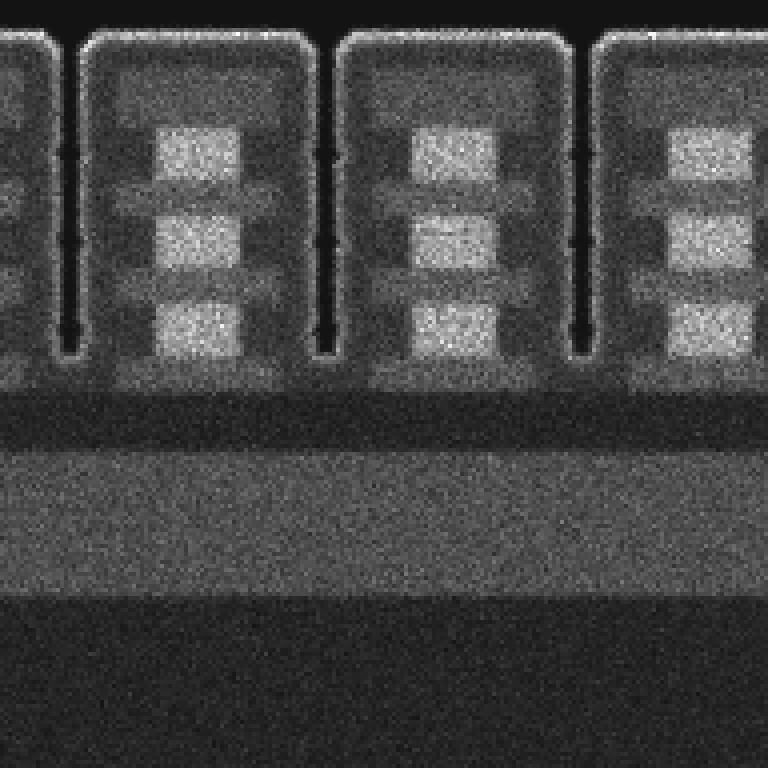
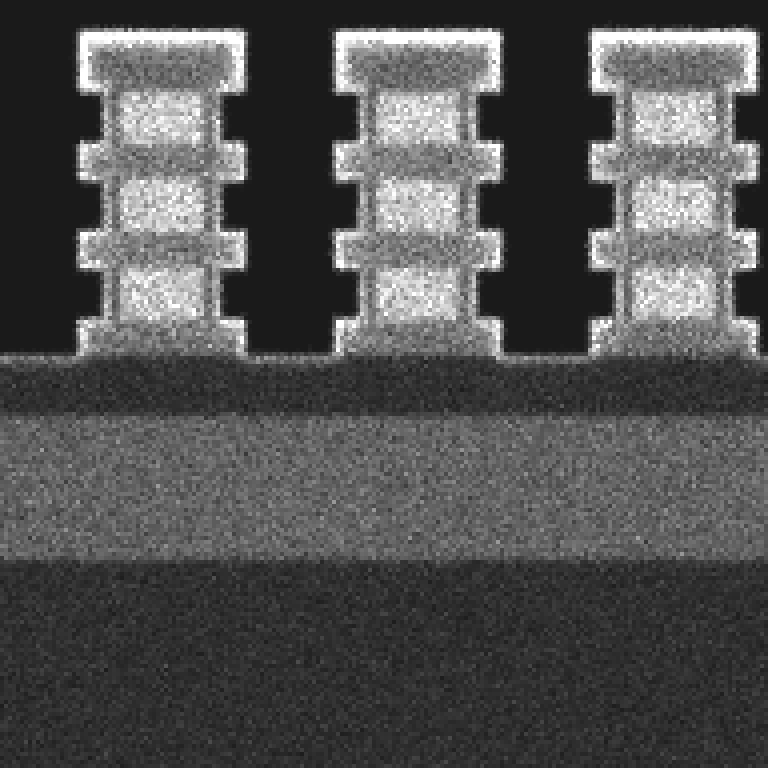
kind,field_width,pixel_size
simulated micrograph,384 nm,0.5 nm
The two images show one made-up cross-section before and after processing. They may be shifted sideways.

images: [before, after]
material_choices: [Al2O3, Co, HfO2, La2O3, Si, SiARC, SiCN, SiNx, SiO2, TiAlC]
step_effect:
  removed: SiNx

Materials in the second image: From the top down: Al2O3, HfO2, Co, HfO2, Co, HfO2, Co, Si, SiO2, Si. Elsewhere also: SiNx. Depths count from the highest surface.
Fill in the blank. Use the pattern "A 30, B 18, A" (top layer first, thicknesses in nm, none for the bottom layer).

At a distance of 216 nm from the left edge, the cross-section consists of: Al2O3 30, HfO2 26, Co 18, HfO2 26, Co 18, HfO2 26, Co 18, Si 30, SiO2 72, Si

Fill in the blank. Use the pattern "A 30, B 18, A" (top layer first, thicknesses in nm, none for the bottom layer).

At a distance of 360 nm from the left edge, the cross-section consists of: Al2O3 30, SiNx 26, Co 18, SiNx 26, Co 18, SiNx 26, Co 18, Si 30, SiO2 72, Si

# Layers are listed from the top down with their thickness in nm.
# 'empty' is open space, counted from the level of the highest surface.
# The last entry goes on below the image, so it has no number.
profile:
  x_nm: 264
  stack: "empty 162, Si 30, SiO2 72, Si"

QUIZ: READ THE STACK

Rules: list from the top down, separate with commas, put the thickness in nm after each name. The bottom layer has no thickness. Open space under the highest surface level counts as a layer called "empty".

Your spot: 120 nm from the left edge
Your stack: Al2O3 30, empty 26, Co 18, empty 26, Co 18, empty 26, Co 18, Si 30, SiO2 72, Si